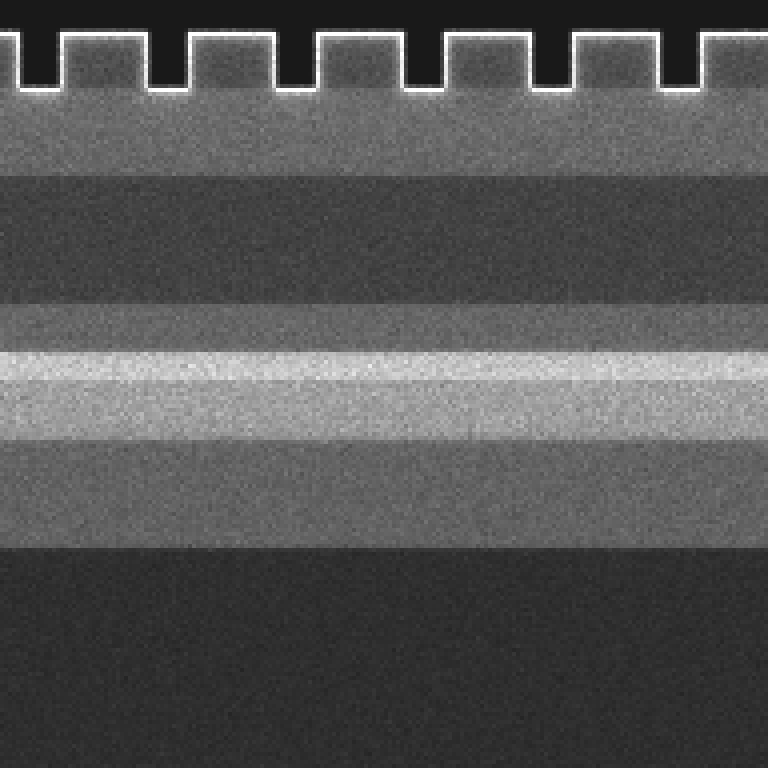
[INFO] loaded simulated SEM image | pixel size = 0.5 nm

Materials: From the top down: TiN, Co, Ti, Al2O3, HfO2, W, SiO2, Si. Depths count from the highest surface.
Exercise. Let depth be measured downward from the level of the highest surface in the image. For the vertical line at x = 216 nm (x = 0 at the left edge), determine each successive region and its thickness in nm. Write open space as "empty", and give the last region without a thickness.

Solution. empty 28, Co 44, Ti 64, Al2O3 24, HfO2 14, W 30, SiO2 54, Si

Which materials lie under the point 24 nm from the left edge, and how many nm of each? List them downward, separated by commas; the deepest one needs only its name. empty 28, Co 44, Ti 64, Al2O3 24, HfO2 14, W 30, SiO2 54, Si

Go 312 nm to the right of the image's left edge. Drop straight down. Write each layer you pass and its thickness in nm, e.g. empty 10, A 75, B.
TiN 28, Co 44, Ti 64, Al2O3 24, HfO2 14, W 30, SiO2 54, Si